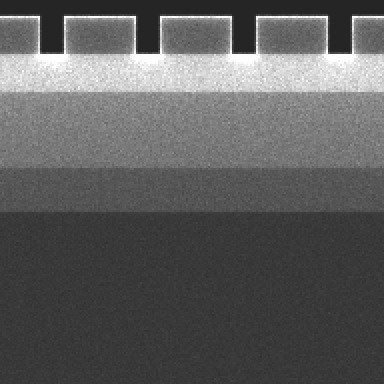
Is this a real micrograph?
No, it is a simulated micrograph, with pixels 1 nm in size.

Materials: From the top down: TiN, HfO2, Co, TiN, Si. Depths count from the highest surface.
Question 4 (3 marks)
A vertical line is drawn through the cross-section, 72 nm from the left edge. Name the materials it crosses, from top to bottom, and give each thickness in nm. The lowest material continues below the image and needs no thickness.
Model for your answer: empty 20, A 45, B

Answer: TiN 38, HfO2 38, Co 76, TiN 44, Si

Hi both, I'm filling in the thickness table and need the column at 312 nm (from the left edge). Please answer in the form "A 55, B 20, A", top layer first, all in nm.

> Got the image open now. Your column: TiN 38, HfO2 38, Co 76, TiN 44, Si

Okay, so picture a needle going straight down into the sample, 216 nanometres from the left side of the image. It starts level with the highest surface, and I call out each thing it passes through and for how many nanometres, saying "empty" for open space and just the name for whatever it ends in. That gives TiN 38, HfO2 38, Co 76, TiN 44, Si